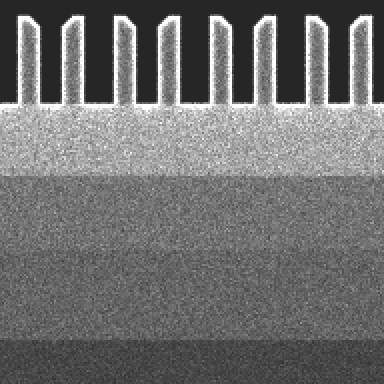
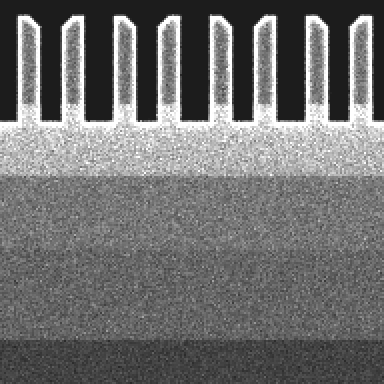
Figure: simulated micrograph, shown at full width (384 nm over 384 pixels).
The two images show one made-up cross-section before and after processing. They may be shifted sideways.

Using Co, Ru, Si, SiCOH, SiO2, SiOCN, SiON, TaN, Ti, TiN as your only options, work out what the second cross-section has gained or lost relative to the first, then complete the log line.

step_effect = removed Co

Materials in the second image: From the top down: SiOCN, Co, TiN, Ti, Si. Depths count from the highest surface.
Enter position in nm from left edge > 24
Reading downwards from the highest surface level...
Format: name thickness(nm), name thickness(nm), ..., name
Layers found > SiOCN 88, Co 72, TiN 74, Ti 90, Si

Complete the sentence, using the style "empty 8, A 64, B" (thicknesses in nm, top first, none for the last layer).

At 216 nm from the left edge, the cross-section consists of SiOCN 88, Co 72, TiN 74, Ti 90, Si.